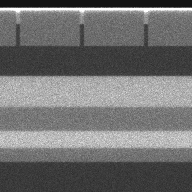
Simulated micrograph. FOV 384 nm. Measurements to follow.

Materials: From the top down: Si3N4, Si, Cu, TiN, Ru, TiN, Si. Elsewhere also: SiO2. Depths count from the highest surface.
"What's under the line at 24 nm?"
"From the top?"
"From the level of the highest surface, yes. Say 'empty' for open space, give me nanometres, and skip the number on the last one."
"Si3N4 76, Si 60, Cu 62, TiN 48, Ru 34, TiN 28, Si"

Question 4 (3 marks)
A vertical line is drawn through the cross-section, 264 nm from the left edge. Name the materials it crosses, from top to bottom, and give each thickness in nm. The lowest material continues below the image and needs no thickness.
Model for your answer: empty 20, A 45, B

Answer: Si3N4 76, Si 60, Cu 62, TiN 48, Ru 34, TiN 28, Si